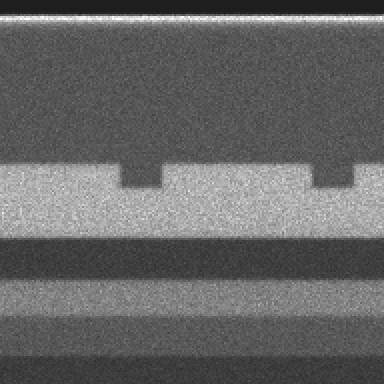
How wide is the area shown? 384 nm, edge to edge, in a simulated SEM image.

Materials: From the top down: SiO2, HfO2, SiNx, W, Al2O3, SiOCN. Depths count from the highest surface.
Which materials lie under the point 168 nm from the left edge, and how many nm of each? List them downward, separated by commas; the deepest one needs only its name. SiO2 148, HfO2 74, SiNx 42, W 36, Al2O3 40, SiOCN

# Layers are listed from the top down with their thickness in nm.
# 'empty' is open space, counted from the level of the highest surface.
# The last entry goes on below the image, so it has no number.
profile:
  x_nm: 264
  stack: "SiO2 148, HfO2 74, SiNx 42, W 36, Al2O3 40, SiOCN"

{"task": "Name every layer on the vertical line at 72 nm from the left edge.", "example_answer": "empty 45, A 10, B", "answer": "SiO2 148, HfO2 74, SiNx 42, W 36, Al2O3 40, SiOCN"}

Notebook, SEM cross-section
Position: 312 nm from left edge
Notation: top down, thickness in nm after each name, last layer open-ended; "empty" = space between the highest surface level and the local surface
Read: SiO2 172, HfO2 50, SiNx 42, W 36, Al2O3 40, SiOCN